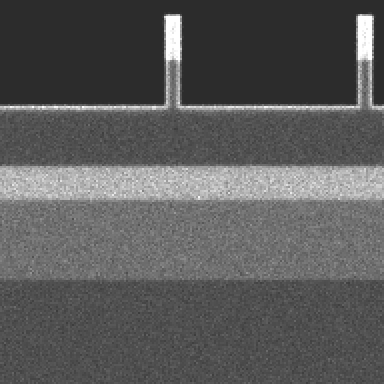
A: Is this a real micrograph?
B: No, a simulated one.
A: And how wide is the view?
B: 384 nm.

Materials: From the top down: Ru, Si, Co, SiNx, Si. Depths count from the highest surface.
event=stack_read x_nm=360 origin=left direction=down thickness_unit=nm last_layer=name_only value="Ru 44, Si 106, Co 34, SiNx 80, Si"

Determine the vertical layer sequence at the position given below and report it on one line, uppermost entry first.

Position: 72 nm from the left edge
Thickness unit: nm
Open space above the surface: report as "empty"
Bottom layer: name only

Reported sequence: empty 90, Si 60, Co 34, SiNx 80, Si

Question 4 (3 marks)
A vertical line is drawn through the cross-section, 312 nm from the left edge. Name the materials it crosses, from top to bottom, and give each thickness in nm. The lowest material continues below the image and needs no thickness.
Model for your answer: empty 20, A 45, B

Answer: empty 90, Si 60, Co 34, SiNx 80, Si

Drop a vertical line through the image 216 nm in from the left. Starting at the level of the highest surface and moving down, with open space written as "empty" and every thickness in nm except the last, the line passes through empty 90, Si 60, Co 34, SiNx 80, Si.